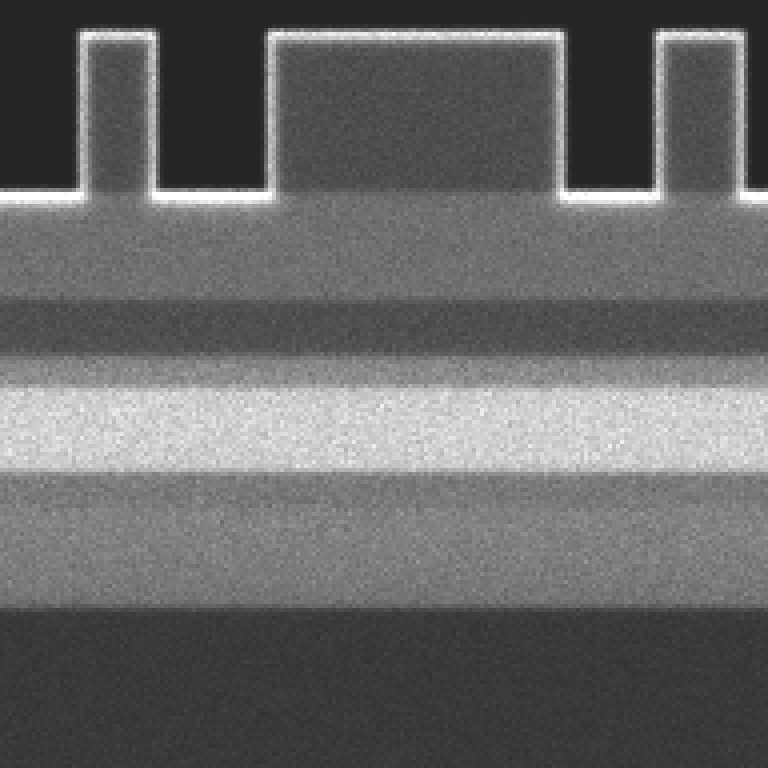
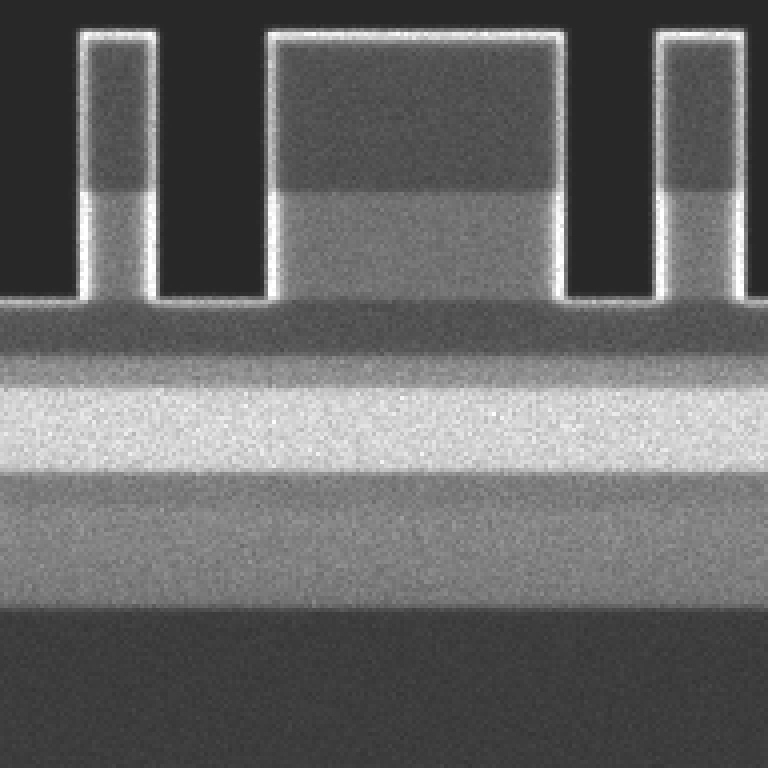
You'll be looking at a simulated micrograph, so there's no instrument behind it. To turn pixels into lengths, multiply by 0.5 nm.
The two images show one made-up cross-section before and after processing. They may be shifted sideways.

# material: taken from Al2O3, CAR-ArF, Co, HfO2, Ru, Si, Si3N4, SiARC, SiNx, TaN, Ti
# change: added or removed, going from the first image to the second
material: Al2O3
change: removed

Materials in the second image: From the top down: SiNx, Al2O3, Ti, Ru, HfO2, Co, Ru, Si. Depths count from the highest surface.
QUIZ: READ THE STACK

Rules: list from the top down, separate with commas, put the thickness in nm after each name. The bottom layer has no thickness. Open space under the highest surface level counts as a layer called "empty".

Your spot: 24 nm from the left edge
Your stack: empty 134, Ti 28, Ru 16, HfO2 42, Co 18, Ru 50, Si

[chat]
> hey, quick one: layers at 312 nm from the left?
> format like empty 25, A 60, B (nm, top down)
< empty 134, Ti 28, Ru 16, HfO2 42, Co 18, Ru 50, Si